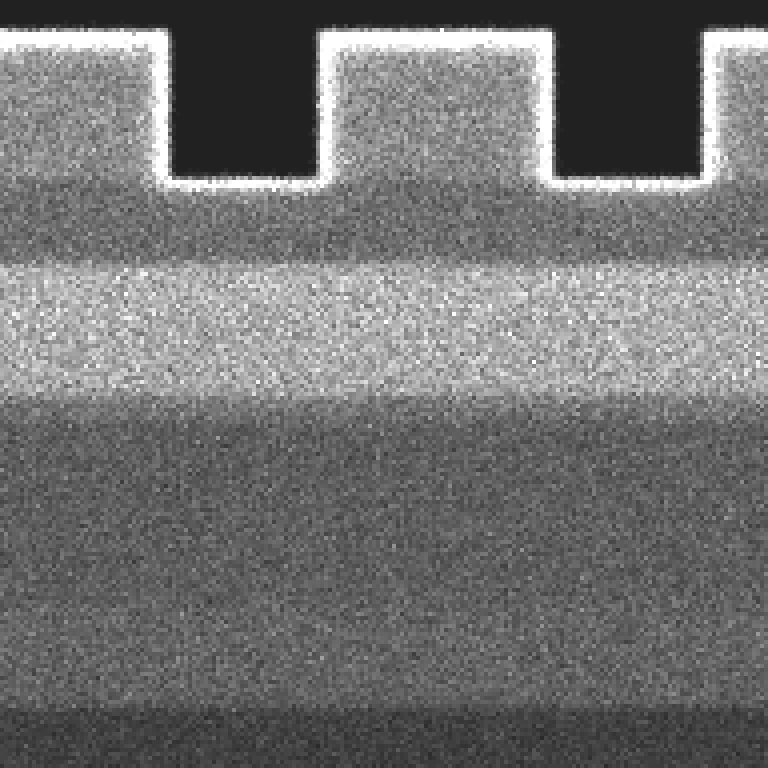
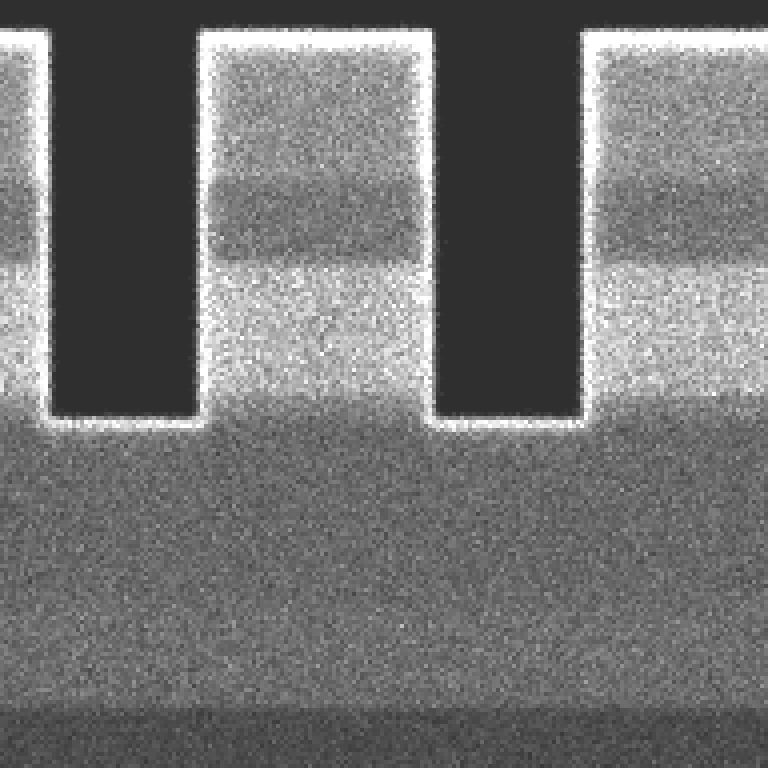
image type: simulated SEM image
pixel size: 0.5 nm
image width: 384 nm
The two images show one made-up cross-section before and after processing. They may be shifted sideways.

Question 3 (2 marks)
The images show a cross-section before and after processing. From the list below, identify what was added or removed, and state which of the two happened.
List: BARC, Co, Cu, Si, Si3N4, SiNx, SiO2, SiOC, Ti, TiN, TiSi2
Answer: Co and Si3N4 and TiN was removed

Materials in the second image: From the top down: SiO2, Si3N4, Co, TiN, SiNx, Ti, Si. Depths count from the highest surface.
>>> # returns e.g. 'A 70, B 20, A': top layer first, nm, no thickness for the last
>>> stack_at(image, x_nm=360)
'SiO2 74, Si3N4 42, Co 66, TiN 12, SiNx 92, Ti 52, Si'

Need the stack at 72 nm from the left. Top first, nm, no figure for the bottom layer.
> empty 194, SiNx 92, Ti 52, Si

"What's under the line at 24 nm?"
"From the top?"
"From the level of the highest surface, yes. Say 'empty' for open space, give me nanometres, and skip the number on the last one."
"empty 194, SiNx 92, Ti 52, Si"